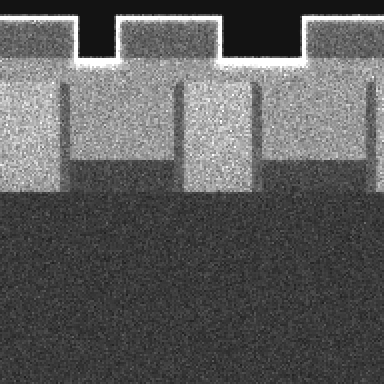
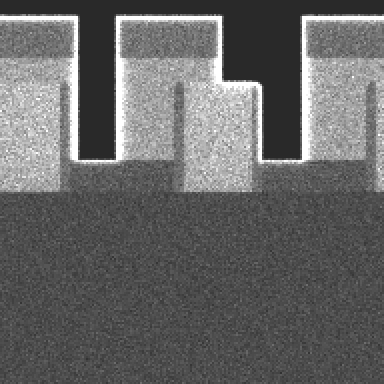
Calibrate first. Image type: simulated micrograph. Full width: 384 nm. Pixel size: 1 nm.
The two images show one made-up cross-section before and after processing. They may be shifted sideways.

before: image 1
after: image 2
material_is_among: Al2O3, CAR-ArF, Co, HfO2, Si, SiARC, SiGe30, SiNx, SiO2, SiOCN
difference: SiO2, removed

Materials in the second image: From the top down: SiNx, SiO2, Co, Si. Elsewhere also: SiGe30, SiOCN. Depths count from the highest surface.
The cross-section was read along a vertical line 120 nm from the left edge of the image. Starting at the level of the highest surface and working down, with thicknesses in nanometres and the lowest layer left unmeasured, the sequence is SiNx 42, SiO2 102, SiGe30 32, Si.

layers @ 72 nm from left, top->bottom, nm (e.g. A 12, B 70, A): SiNx 42, SiO2 102, SiGe30 32, Si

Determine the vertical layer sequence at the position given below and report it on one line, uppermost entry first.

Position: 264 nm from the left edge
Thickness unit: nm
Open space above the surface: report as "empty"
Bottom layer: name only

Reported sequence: empty 144, SiGe30 32, Si